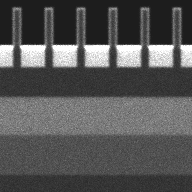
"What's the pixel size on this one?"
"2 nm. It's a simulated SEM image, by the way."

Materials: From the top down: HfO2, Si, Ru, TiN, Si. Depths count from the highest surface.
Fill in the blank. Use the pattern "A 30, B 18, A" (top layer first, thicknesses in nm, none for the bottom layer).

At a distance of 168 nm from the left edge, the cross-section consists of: Si 178, Ru 76, TiN 80, Si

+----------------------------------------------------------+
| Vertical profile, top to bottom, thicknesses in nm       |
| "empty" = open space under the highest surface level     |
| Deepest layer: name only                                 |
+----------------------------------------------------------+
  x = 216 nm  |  empty 76, HfO2 42, Si 60, Ru 76, TiN 80, Si